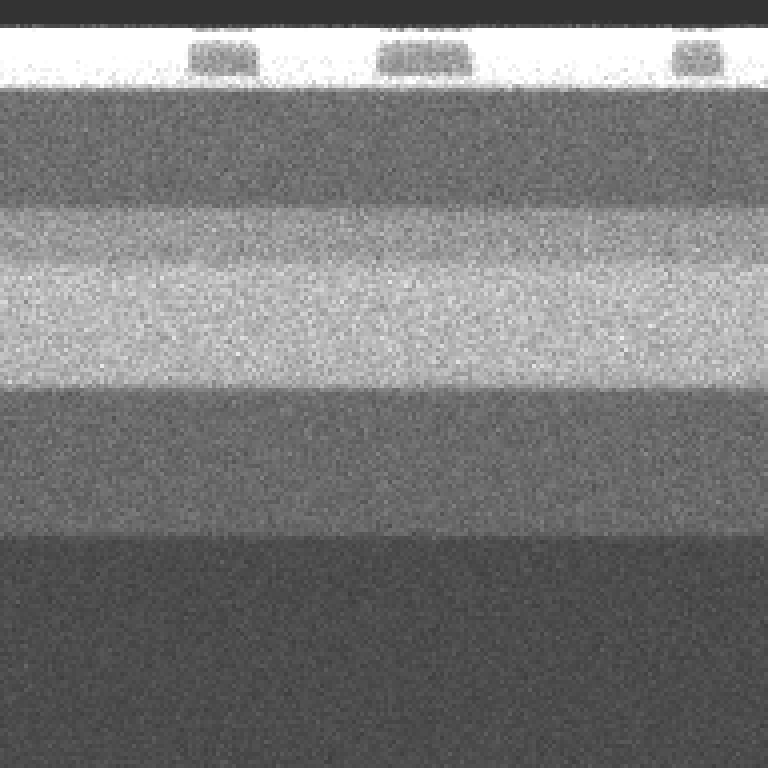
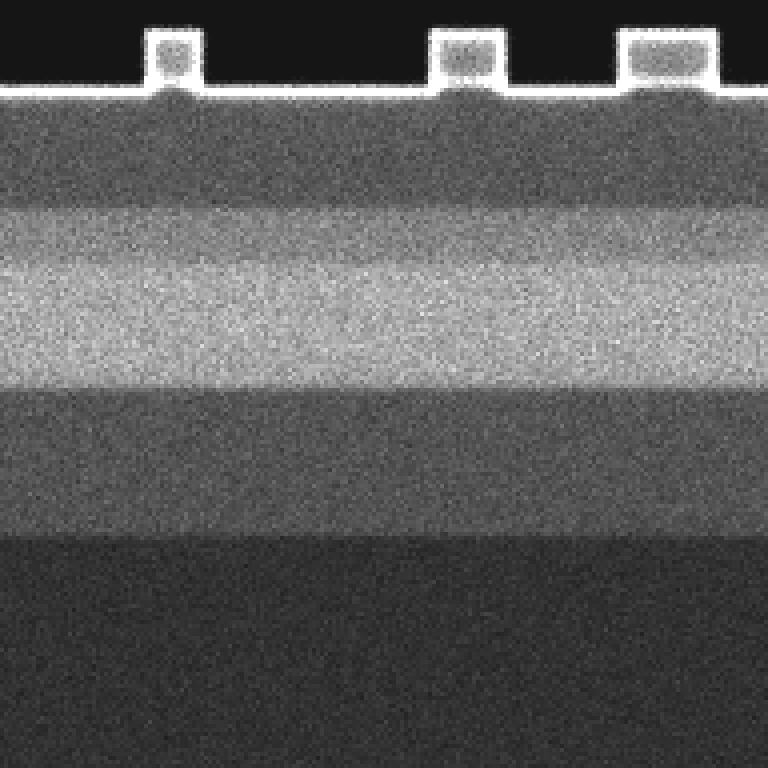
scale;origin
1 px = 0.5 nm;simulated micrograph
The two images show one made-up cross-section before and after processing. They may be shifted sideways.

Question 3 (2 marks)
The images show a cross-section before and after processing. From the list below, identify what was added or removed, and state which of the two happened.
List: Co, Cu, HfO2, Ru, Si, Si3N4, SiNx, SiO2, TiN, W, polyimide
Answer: HfO2 was removed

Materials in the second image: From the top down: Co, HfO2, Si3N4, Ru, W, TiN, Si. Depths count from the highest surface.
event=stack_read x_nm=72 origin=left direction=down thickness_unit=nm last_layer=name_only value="empty 28, Si3N4 60, Ru 28, W 62, TiN 74, Si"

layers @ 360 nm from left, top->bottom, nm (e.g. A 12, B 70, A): empty 28, Si3N4 60, Ru 28, W 62, TiN 74, Si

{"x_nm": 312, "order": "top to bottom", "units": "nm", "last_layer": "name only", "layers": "Co 22, HfO2 6, Si3N4 60, Ru 28, W 62, TiN 74, Si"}